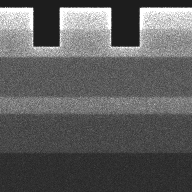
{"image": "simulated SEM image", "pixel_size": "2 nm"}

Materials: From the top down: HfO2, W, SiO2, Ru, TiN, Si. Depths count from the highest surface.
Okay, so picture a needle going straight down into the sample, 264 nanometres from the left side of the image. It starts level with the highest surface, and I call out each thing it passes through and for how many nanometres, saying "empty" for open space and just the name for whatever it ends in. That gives empty 78, W 20, SiO2 80, Ru 34, TiN 78, Si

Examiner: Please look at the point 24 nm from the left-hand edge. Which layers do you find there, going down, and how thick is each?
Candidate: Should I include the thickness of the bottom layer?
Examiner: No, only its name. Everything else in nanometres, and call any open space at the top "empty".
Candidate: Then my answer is HfO2 42, W 56, SiO2 80, Ru 34, TiN 78, Si